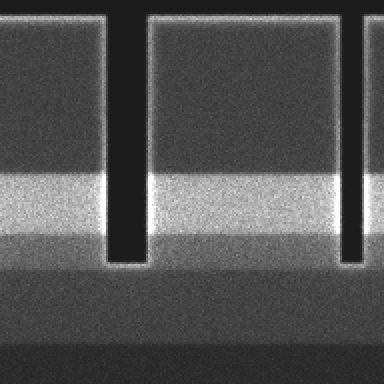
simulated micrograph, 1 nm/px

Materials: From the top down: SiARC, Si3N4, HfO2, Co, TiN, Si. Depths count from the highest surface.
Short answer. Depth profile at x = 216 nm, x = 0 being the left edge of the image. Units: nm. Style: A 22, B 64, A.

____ SiARC 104, Si3N4 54, HfO2 60, Co 36, TiN 74, Si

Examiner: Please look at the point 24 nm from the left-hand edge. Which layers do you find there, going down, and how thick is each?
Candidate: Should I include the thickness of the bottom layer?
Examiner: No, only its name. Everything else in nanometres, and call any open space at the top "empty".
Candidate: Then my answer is SiARC 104, Si3N4 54, HfO2 60, Co 36, TiN 74, Si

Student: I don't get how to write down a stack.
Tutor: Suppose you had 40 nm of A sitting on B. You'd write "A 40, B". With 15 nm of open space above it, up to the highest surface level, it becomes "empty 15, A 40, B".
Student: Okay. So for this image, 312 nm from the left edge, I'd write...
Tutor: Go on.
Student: SiARC 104, Si3N4 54, HfO2 60, Co 36, TiN 74, Si